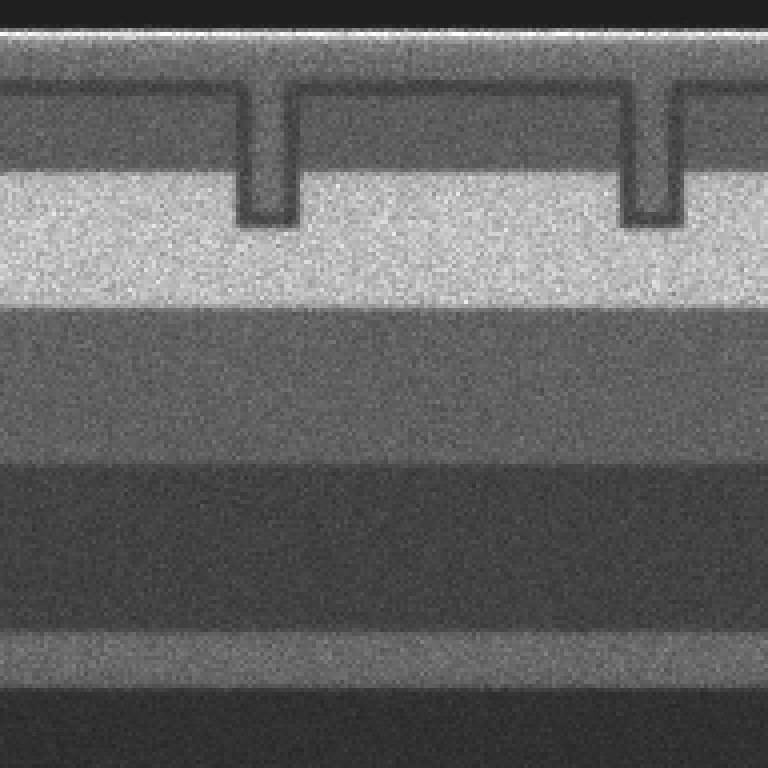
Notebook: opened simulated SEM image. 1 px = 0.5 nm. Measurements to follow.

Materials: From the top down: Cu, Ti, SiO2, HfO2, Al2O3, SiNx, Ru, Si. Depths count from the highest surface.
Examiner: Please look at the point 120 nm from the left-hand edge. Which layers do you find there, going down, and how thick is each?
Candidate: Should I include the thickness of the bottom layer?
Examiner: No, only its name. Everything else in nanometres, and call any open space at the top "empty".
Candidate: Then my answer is Cu 24, Ti 74, HfO2 40, Al2O3 78, SiNx 84, Ru 28, Si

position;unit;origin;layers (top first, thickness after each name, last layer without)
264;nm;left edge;Cu 24, Ti 8, SiO2 38, HfO2 68, Al2O3 78, SiNx 84, Ru 28, Si